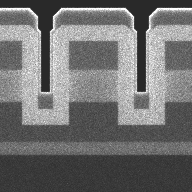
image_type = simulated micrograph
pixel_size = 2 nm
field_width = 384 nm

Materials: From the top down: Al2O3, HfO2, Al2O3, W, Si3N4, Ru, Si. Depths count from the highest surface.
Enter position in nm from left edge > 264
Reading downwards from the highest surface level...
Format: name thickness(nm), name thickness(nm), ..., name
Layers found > empty 14, Al2O3 34, HfO2 186, Si3N4 34, Ru 26, Si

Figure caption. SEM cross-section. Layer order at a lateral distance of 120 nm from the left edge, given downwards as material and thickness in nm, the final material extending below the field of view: empty 2, Al2O3 34, HfO2 198, Si3N4 34, Ru 26, Si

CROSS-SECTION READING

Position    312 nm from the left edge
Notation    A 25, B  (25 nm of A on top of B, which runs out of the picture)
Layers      empty 2, Al2O3 34, HfO2 198, Si3N4 34, Ru 26, Si